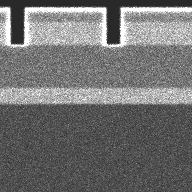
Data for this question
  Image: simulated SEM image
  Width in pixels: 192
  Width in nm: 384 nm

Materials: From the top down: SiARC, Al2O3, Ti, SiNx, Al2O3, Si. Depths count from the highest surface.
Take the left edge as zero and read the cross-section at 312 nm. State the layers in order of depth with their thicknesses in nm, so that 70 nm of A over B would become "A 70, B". SiARC 28, Al2O3 46, Ti 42, SiNx 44, Al2O3 32, Si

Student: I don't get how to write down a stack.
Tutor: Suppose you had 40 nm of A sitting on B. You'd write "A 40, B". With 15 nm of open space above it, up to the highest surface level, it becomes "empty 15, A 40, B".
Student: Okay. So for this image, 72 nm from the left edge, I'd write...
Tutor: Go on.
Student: SiARC 28, Al2O3 46, Ti 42, SiNx 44, Al2O3 32, Si